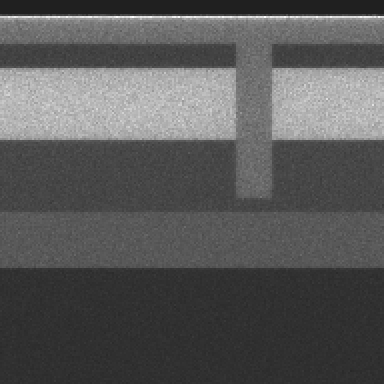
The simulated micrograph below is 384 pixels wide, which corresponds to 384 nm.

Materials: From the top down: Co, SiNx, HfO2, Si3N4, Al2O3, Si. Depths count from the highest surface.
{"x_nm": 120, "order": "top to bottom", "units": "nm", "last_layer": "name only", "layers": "Co 28, SiNx 24, HfO2 72, Si3N4 72, Al2O3 56, Si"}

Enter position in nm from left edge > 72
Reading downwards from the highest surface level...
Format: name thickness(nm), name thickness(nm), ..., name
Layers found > Co 28, SiNx 24, HfO2 72, Si3N4 72, Al2O3 56, Si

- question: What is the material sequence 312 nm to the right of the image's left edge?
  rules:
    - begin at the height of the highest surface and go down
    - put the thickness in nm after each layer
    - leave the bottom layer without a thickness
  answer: Co 28, SiNx 24, HfO2 72, Si3N4 72, Al2O3 56, Si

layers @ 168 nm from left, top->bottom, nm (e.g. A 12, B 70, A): Co 28, SiNx 24, HfO2 72, Si3N4 72, Al2O3 56, Si